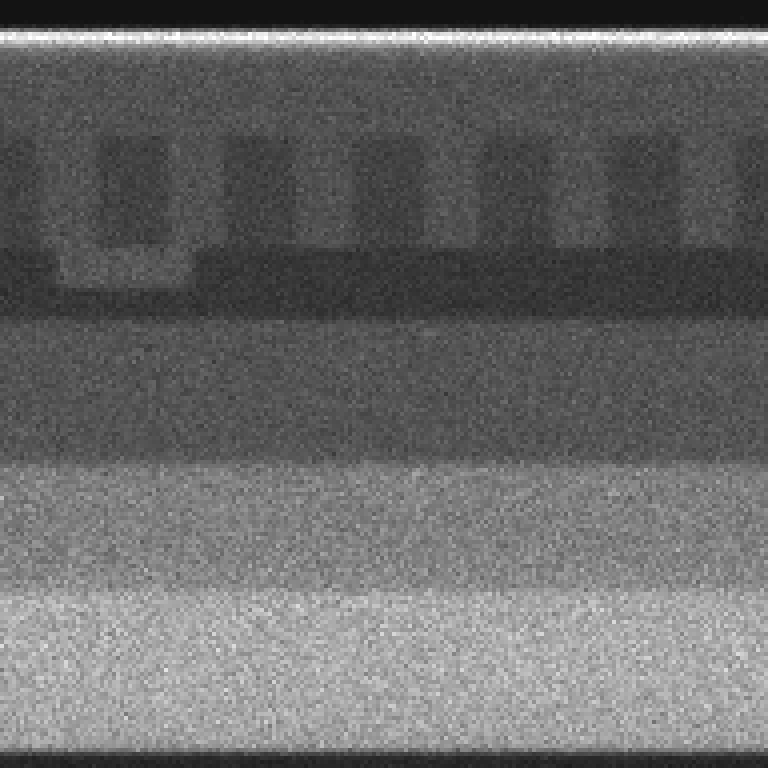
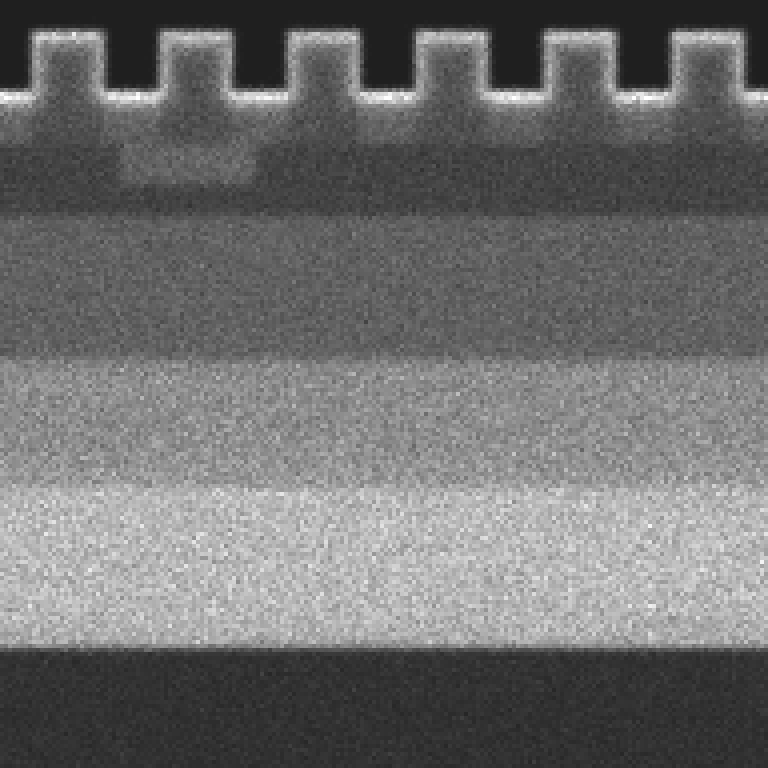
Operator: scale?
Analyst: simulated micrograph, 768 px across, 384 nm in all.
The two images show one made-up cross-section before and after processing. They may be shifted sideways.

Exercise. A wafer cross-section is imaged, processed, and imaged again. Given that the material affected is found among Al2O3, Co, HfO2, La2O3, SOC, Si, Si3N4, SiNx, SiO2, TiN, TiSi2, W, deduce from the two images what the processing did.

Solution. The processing removed SiO2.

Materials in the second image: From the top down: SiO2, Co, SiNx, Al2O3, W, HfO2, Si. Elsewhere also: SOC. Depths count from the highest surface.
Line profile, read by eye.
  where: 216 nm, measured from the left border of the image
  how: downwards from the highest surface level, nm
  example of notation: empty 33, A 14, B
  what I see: SOC 56, SiNx 36, Al2O3 72, W 64, HfO2 80, Si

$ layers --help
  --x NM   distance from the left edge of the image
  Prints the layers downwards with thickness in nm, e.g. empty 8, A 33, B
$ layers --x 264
empty 30, SiO2 26, SiNx 36, Al2O3 72, W 64, HfO2 80, Si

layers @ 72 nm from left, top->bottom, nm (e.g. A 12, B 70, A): empty 30, SiO2 26, Co 20, SiNx 16, Al2O3 72, W 64, HfO2 80, Si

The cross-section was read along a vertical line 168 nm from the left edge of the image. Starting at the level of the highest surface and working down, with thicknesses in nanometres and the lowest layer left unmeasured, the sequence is SOC 56, SiNx 36, Al2O3 72, W 64, HfO2 80, Si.